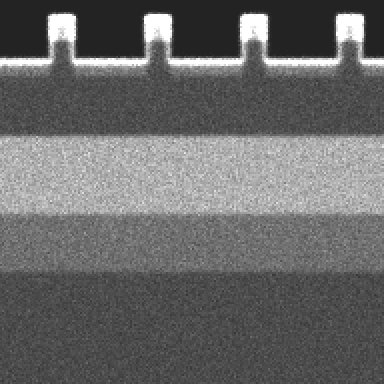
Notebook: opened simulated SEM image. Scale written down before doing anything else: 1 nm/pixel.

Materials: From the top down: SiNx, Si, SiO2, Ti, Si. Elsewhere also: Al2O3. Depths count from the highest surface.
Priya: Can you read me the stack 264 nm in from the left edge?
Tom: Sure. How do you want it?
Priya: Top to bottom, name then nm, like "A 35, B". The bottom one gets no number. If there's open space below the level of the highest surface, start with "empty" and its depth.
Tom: Al2O3 24, Si 96, SiO2 78, Ti 58, Si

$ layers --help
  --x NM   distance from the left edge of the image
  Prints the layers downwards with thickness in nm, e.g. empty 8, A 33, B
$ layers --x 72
Al2O3 24, Si 96, SiO2 78, Ti 58, Si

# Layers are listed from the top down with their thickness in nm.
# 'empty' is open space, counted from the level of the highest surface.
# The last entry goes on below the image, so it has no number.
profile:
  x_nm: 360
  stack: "Al2O3 24, Si 96, SiO2 78, Ti 58, Si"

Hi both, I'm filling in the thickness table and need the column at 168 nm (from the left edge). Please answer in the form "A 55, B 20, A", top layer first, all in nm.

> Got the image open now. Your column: Al2O3 24, Si 96, SiO2 78, Ti 58, Si